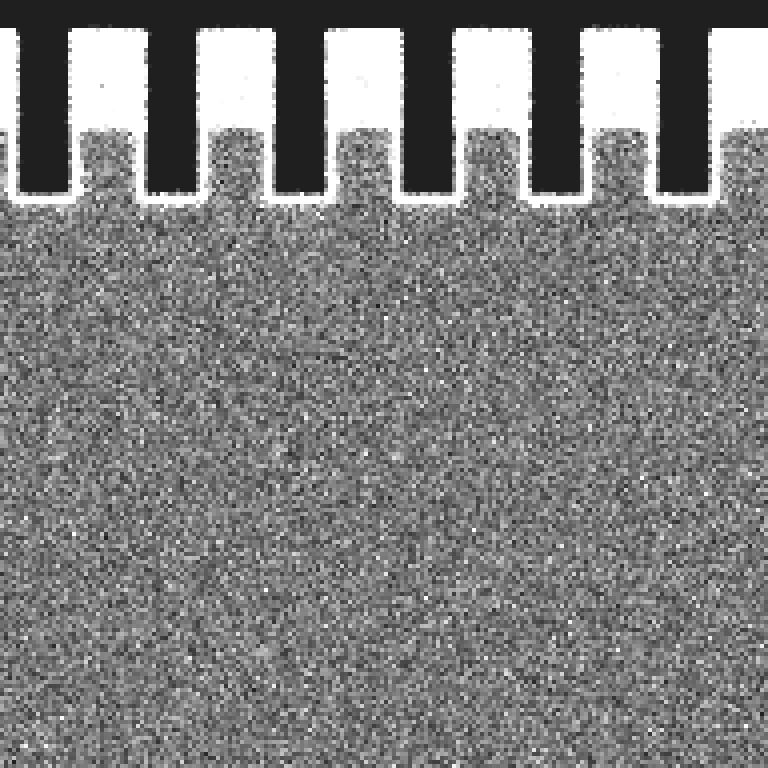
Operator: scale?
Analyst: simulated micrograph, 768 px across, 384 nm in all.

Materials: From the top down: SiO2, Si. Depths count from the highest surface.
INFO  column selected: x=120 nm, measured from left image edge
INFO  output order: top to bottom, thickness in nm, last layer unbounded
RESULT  SiO2 48, Si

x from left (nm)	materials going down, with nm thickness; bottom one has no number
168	SiO2 48, Si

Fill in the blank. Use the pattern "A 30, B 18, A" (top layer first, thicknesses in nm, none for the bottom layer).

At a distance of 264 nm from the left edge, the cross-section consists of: empty 82, Si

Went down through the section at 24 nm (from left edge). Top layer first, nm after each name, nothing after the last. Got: empty 82, Si